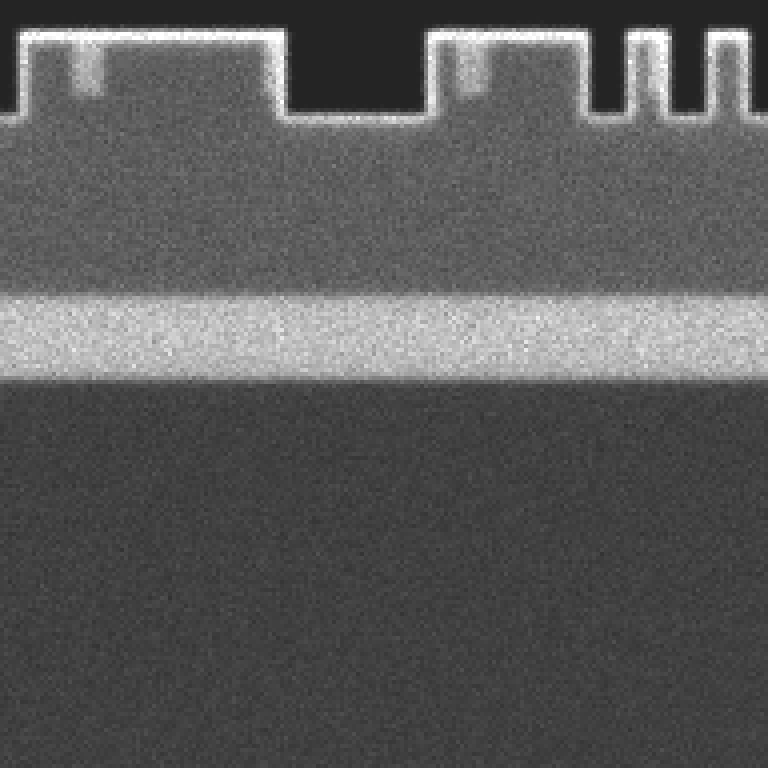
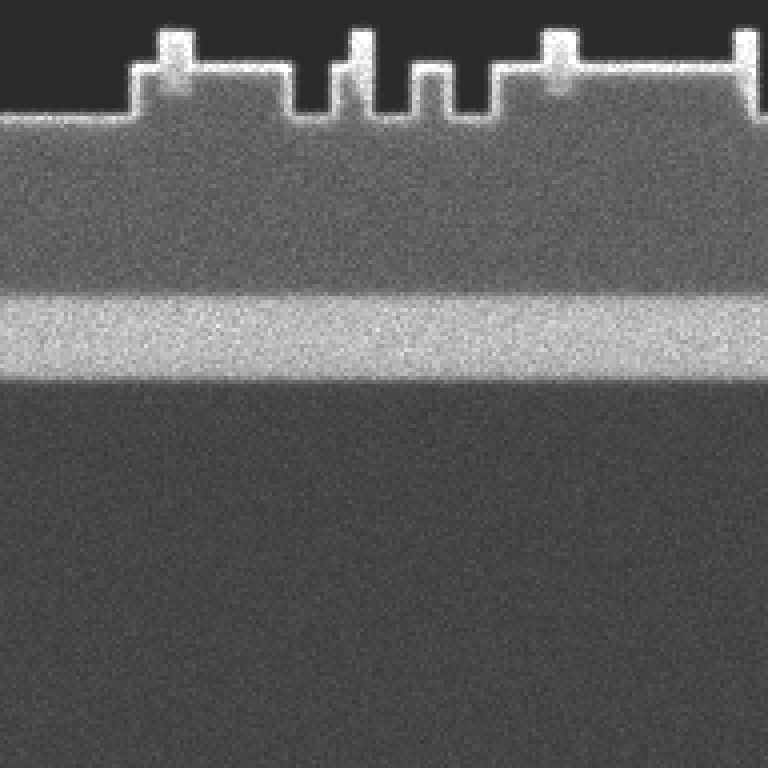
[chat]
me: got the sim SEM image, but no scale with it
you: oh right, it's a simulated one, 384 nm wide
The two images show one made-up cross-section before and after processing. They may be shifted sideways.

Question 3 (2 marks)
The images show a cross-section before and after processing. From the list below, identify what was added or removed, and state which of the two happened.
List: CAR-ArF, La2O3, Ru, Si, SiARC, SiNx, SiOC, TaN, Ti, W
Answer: SiNx was removed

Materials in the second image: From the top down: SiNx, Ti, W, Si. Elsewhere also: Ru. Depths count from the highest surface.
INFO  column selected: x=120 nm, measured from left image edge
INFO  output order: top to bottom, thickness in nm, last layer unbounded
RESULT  empty 16, SiNx 26, Ti 90, W 42, Si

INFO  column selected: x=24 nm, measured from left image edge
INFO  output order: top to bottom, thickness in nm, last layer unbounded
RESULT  empty 42, Ti 90, W 42, Si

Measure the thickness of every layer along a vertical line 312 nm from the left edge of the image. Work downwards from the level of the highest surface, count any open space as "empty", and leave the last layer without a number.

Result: empty 16, SiNx 26, Ti 90, W 42, Si